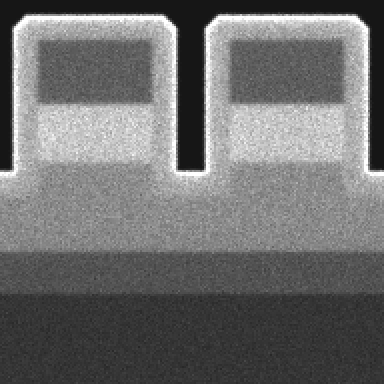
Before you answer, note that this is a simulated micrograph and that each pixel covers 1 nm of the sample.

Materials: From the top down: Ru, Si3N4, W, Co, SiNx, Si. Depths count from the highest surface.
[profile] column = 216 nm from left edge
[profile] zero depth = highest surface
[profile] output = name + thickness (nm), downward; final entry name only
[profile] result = empty 2, Ru 178, Co 56, SiNx 42, Si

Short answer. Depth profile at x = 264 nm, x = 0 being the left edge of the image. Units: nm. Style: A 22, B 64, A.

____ Ru 24, Si3N4 64, W 58, Co 90, SiNx 42, Si